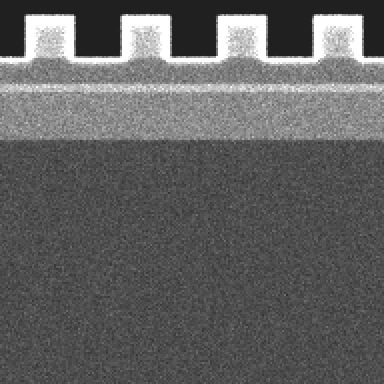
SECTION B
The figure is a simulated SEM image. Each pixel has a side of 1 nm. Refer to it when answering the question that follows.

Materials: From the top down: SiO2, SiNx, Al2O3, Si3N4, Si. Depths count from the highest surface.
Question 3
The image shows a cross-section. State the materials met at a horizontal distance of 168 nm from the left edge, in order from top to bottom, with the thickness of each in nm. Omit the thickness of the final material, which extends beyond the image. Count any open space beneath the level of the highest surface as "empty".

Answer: SiO2 42, SiNx 26, Al2O3 8, Si3N4 48, Si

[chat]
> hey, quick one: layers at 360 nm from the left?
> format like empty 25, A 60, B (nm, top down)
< SiO2 42, SiNx 26, Al2O3 8, Si3N4 48, Si